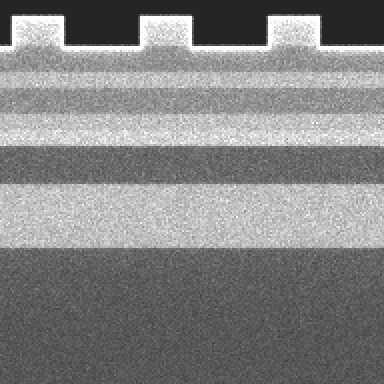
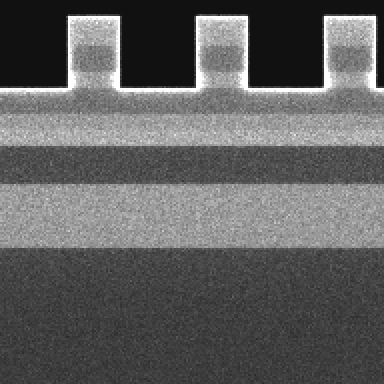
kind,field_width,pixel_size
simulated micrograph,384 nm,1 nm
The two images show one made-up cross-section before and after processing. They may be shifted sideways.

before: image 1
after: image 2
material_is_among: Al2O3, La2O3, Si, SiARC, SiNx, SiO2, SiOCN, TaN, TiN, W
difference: SiNx and SiO2, removed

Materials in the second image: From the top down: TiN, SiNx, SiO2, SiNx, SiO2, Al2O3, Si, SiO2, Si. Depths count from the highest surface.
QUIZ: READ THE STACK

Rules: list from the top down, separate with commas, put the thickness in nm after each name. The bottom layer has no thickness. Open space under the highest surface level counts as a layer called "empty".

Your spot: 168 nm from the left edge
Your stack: empty 72, SiNx 26, SiO2 16, Al2O3 16, Si 38, SiO2 64, Si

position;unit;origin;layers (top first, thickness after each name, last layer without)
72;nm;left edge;TiN 30, SiNx 26, SiO2 16, SiNx 26, SiO2 16, Al2O3 16, Si 38, SiO2 64, Si